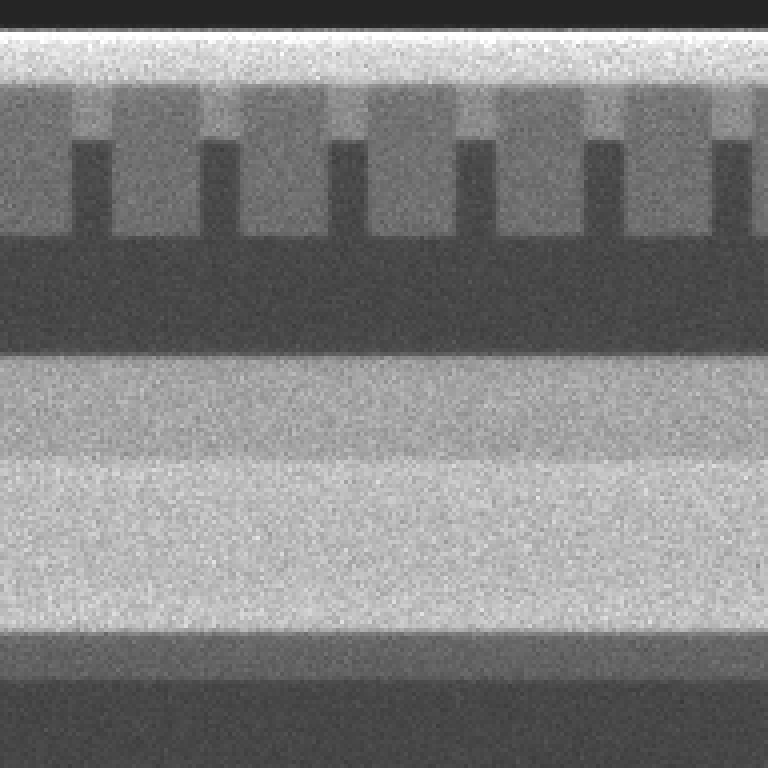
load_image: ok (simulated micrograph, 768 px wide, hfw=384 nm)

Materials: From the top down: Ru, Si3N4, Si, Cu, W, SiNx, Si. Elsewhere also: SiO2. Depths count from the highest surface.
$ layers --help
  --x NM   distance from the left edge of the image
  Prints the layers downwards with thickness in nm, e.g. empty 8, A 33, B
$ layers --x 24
Ru 26, Si3N4 76, Si 60, Cu 52, W 86, SiNx 24, Si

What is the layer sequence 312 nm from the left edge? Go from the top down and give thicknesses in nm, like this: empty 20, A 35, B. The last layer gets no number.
Ru 26, Si3N4 76, Si 60, Cu 52, W 86, SiNx 24, Si